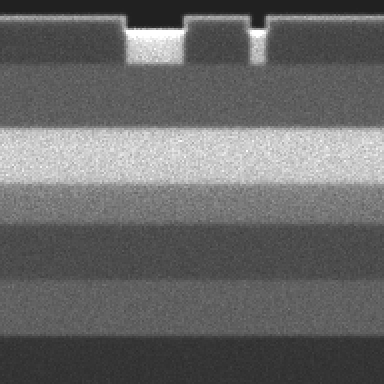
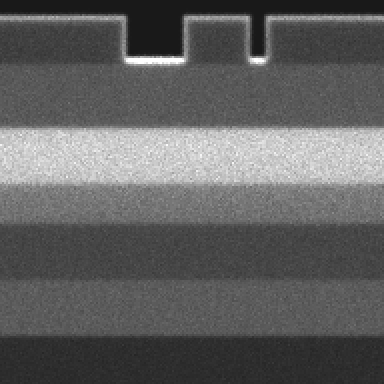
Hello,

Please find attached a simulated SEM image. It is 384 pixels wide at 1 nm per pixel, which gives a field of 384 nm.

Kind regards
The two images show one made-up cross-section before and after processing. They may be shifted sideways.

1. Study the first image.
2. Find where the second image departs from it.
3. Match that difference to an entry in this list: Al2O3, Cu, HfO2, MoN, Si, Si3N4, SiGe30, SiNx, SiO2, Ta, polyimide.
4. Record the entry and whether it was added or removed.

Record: HfO2 / removed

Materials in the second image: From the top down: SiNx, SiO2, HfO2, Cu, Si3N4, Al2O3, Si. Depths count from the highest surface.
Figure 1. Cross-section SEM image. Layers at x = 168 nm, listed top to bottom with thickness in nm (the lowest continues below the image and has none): empty 42, HfO2 6, SiO2 64, HfO2 56, Cu 40, Si3N4 56, Al2O3 56, Si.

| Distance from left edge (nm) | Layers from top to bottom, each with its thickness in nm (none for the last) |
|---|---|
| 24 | SiNx 48, SiO2 64, HfO2 56, Cu 40, Si3N4 56, Al2O3 56, Si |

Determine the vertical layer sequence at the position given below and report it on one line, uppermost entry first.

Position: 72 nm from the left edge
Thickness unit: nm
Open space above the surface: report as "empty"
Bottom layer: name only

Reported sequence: SiNx 48, SiO2 64, HfO2 56, Cu 40, Si3N4 56, Al2O3 56, Si